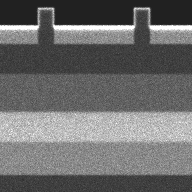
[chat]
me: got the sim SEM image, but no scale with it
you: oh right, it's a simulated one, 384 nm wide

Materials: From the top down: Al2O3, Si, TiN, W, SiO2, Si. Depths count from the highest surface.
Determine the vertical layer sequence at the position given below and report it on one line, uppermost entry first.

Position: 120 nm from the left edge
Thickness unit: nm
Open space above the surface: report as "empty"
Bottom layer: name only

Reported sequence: empty 36, Al2O3 36, Si 60, TiN 76, W 60, SiO2 66, Si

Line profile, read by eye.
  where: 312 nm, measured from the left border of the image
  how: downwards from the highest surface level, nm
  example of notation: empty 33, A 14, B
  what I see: empty 36, Al2O3 36, Si 60, TiN 76, W 60, SiO2 66, Si